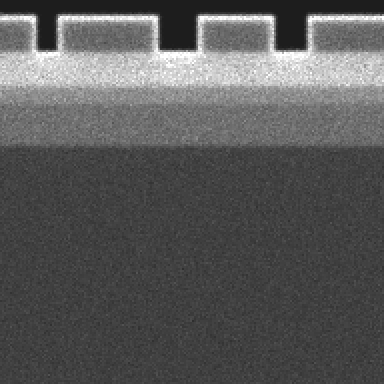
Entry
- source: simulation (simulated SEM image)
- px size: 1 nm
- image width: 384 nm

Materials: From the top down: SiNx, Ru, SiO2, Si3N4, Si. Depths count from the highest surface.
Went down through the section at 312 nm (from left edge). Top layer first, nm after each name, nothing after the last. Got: SiNx 36, Ru 34, SiO2 18, Si3N4 42, Si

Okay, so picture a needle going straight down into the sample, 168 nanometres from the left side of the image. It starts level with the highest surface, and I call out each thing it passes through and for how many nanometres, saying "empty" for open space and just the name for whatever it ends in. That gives empty 36, Ru 34, SiO2 18, Si3N4 42, Si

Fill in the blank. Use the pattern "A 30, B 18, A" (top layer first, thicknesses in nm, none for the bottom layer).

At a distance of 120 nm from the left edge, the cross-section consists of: SiNx 36, Ru 34, SiO2 18, Si3N4 42, Si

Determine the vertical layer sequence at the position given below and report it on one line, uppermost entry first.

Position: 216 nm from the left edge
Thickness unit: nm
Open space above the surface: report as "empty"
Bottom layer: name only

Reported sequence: SiNx 36, Ru 34, SiO2 18, Si3N4 42, Si